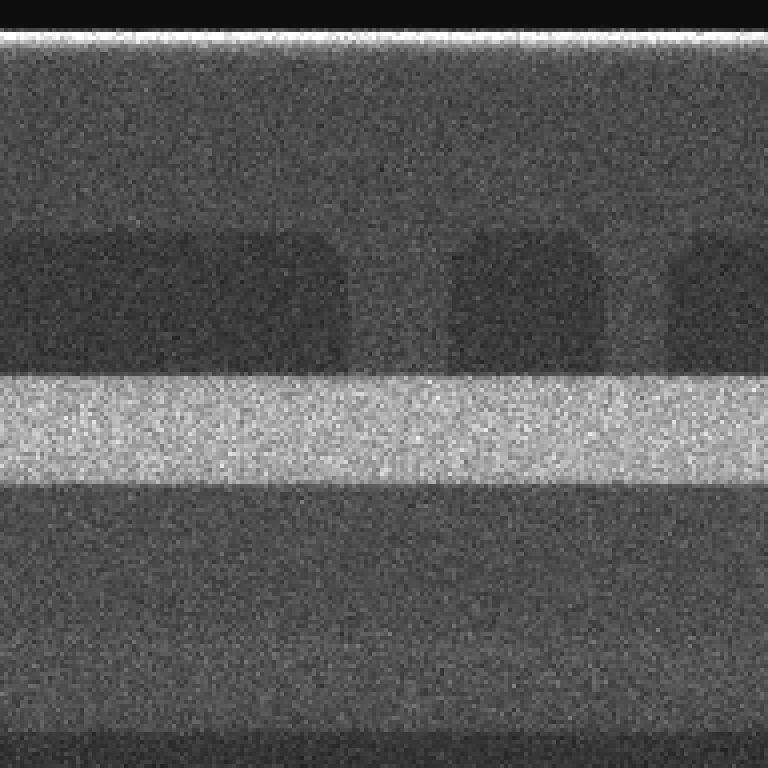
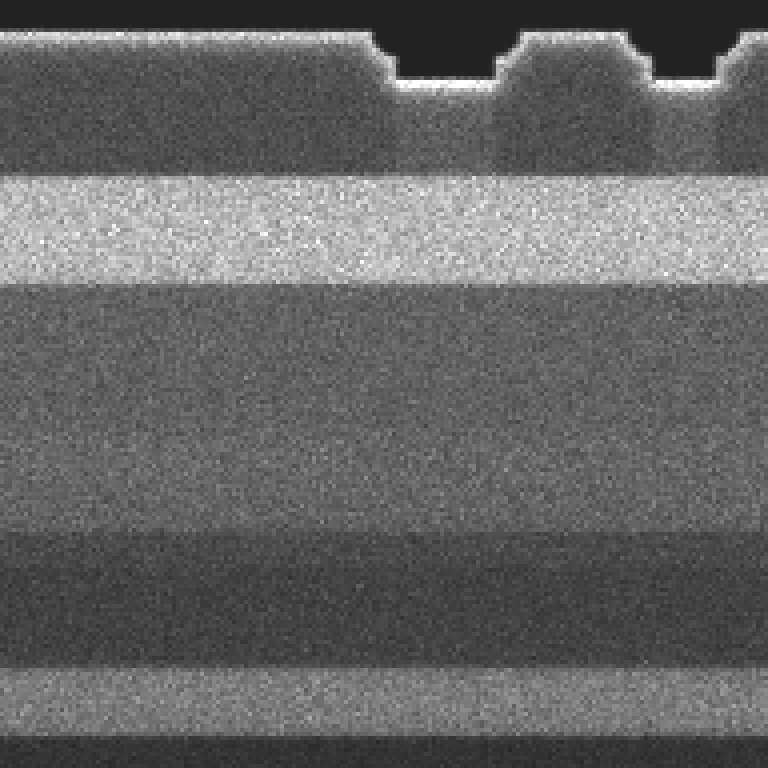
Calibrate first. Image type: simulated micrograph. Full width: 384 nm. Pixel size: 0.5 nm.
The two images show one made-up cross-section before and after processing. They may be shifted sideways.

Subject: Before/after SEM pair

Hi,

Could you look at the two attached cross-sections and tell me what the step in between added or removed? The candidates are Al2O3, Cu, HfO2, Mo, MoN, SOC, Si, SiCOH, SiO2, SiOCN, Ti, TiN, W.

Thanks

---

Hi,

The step removed SiO2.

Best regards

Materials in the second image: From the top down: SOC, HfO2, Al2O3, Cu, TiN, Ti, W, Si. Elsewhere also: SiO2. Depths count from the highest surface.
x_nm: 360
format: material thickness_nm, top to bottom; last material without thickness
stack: empty 12, SOC 60, HfO2 54, Al2O3 74, Cu 50, TiN 18, Ti 50, W 34, Si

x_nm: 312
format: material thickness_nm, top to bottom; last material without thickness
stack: SOC 72, HfO2 54, Al2O3 74, Cu 50, TiN 18, Ti 50, W 34, Si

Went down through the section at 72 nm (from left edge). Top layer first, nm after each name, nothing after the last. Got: SOC 72, HfO2 54, Al2O3 74, Cu 50, TiN 18, Ti 50, W 34, Si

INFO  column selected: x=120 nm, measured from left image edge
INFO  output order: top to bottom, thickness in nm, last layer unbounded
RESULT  SOC 72, HfO2 54, Al2O3 74, Cu 50, TiN 18, Ti 50, W 34, Si